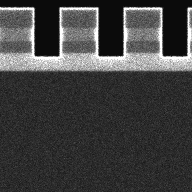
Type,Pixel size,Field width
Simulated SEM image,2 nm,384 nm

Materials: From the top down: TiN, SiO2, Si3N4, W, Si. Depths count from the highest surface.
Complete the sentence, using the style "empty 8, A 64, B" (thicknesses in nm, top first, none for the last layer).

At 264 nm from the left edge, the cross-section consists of TiN 40, SiO2 26, Si3N4 24, W 36, Si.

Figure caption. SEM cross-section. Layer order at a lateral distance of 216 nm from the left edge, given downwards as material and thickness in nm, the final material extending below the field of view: empty 98, W 28, Si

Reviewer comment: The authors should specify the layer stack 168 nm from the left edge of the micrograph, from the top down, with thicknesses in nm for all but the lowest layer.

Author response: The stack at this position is TiN 40, SiO2 26, Si3N4 24, W 36, Si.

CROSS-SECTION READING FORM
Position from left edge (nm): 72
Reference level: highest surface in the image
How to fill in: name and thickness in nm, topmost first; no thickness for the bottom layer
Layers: empty 98, W 28, Si